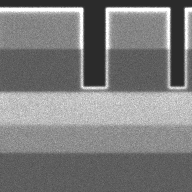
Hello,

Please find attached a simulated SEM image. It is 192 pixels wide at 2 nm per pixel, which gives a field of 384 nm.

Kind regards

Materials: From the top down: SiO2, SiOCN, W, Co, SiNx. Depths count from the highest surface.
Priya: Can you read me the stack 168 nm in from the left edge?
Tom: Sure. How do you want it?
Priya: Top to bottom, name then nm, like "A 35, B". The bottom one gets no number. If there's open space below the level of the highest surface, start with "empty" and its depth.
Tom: empty 158, SiOCN 10, W 66, Co 56, SiNx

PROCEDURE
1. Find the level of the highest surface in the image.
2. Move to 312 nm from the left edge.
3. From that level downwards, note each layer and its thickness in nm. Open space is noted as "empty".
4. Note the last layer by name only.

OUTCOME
SiO2 82, SiOCN 86, W 66, Co 56, SiNx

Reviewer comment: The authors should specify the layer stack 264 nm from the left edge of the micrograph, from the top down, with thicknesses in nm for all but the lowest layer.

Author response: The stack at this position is SiO2 82, SiOCN 86, W 66, Co 56, SiNx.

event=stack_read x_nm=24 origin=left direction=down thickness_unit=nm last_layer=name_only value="SiO2 82, SiOCN 86, W 66, Co 56, SiNx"